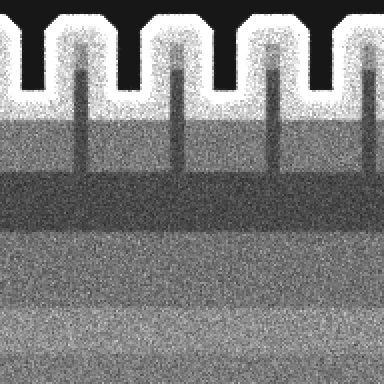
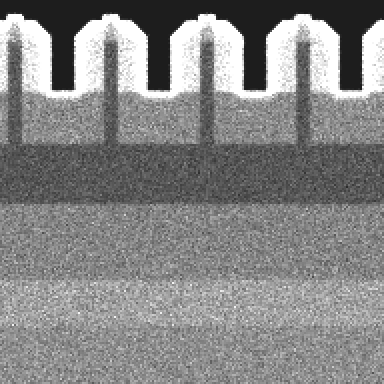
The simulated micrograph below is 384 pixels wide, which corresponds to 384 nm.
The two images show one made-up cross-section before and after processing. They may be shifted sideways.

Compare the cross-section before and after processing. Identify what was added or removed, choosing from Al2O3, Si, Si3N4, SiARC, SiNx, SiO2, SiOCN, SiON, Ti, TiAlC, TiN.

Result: Al2O3 removed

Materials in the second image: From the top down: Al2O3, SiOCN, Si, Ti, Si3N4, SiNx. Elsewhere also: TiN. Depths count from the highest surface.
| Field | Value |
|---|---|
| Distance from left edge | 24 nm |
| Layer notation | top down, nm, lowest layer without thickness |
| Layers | empty 6, Al2O3 70, SiOCN 52, Si 60, Ti 76, Si3N4 46, SiNx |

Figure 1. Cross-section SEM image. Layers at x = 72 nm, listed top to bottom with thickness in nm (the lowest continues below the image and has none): empty 76, SiOCN 52, Si 60, Ti 76, Si3N4 46, SiNx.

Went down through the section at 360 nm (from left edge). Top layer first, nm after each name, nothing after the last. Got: empty 76, SiOCN 52, Si 60, Ti 76, Si3N4 46, SiNx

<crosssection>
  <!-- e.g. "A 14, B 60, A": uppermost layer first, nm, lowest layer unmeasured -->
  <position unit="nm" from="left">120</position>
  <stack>empty 6, Al2O3 70, SiOCN 52, Si 60, Ti 76, Si3N4 46, SiNx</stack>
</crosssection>